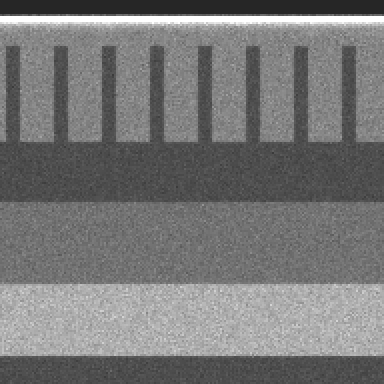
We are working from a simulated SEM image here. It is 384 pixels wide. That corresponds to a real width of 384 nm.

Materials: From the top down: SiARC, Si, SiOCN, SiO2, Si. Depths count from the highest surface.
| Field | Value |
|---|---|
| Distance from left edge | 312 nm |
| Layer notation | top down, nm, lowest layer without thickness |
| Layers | SiARC 126, Si 60, SiOCN 82, SiO2 72, Si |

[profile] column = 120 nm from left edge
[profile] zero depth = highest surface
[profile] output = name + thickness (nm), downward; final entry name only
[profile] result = SiARC 126, Si 60, SiOCN 82, SiO2 72, Si